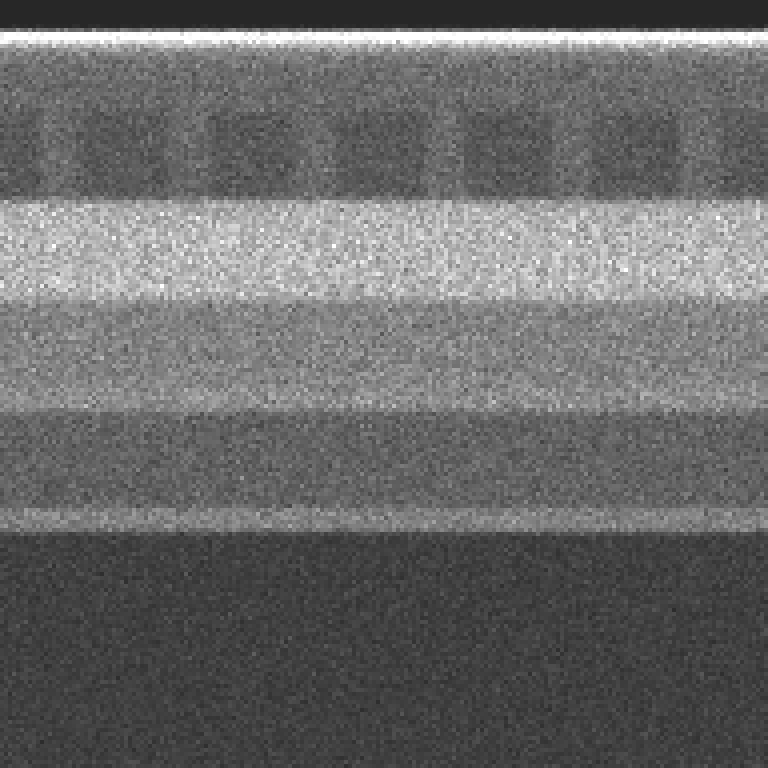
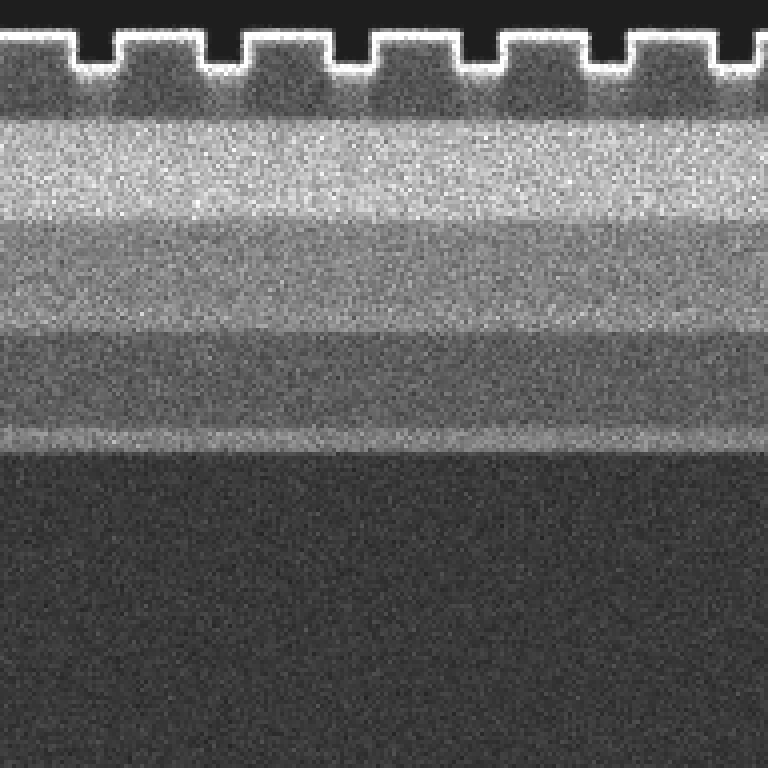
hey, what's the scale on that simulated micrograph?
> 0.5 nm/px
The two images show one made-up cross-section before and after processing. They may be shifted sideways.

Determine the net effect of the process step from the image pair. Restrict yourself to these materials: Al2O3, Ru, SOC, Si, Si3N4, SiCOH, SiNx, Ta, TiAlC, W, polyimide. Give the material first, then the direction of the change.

SOC: removed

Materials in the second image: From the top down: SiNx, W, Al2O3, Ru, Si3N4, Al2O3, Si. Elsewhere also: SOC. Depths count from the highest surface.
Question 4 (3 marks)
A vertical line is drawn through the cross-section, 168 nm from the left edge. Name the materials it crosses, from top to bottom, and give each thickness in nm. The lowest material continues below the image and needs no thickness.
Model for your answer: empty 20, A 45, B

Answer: empty 16, SOC 28, W 50, Al2O3 44, Ru 12, Si3N4 48, Al2O3 12, Si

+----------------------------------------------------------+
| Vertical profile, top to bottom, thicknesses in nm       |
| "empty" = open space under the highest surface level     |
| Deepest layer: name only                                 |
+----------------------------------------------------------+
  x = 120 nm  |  empty 16, SOC 28, W 50, Al2O3 44, Ru 12, Si3N4 48, Al2O3 12, Si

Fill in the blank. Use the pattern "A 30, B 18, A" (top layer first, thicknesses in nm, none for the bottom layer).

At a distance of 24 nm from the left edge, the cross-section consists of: SiNx 44, W 50, Al2O3 44, Ru 12, Si3N4 48, Al2O3 12, Si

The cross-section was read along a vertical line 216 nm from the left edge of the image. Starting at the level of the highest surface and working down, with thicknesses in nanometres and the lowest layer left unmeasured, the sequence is SiNx 44, W 50, Al2O3 44, Ru 12, Si3N4 48, Al2O3 12, Si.